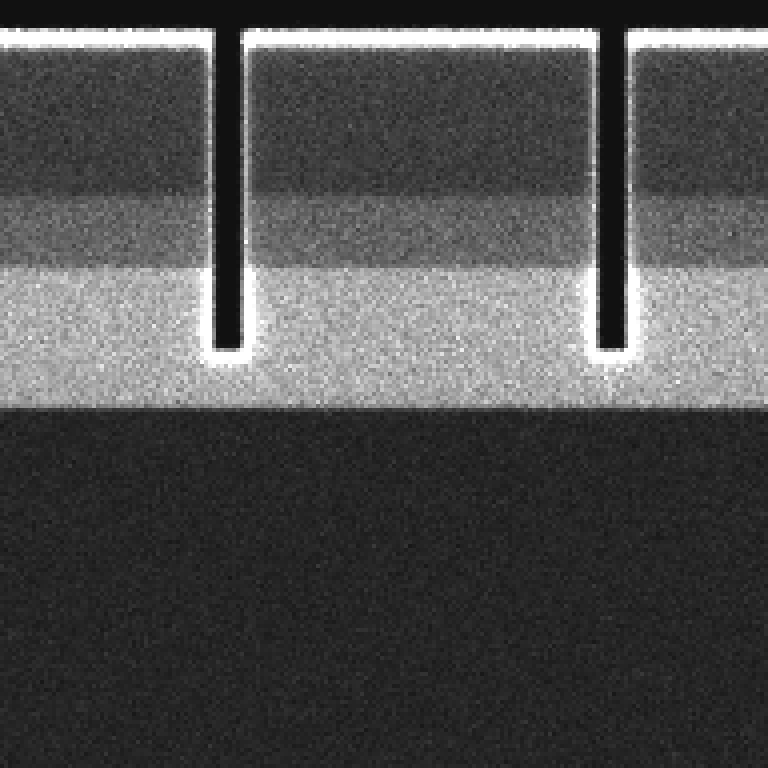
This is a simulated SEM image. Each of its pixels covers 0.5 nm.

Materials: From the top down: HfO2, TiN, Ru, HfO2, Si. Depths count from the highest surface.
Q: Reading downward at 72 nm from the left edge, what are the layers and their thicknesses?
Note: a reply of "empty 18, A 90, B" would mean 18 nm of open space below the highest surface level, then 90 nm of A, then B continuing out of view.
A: HfO2 8, TiN 74, Ru 36, HfO2 70, Si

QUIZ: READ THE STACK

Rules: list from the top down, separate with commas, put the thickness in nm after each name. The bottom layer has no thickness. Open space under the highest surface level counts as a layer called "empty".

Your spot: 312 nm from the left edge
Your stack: empty 160, HfO2 28, Si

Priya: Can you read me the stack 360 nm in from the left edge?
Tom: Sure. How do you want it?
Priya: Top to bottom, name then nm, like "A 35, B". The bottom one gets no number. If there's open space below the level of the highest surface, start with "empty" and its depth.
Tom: HfO2 8, TiN 74, Ru 36, HfO2 70, Si